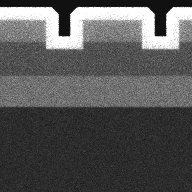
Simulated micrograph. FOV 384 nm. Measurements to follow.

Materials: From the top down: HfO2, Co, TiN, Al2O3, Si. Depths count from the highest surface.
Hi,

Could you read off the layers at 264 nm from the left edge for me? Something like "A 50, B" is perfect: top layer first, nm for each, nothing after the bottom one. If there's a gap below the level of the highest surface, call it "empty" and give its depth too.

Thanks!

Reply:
HfO2 24, Co 44, TiN 68, Al2O3 62, Si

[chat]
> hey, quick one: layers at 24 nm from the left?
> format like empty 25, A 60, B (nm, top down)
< HfO2 24, Co 44, TiN 68, Al2O3 62, Si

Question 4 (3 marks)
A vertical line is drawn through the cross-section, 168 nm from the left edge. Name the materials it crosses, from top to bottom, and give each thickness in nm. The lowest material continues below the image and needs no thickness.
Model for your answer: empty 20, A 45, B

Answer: HfO2 24, Co 44, TiN 68, Al2O3 62, Si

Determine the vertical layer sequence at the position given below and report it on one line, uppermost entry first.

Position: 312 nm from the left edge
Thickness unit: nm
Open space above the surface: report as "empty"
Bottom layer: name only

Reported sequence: empty 58, HfO2 24, TiN 54, Al2O3 62, Si